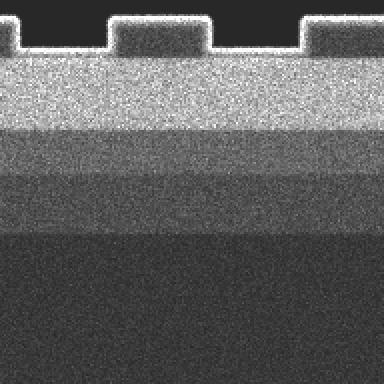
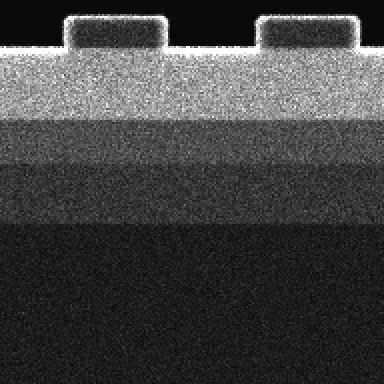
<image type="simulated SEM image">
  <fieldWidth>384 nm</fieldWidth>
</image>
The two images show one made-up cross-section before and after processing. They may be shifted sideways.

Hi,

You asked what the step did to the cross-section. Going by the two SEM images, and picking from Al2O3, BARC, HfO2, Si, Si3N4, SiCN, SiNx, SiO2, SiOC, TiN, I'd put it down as SiO2, removed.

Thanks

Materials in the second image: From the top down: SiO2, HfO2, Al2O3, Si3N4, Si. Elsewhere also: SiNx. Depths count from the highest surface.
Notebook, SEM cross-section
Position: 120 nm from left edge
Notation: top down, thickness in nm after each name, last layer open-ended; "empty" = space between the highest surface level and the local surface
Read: SiNx 32, HfO2 72, Al2O3 44, Si3N4 60, Si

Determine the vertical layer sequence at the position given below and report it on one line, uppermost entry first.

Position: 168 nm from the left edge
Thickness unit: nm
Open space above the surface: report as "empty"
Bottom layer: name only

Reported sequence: empty 32, HfO2 72, Al2O3 44, Si3N4 60, Si